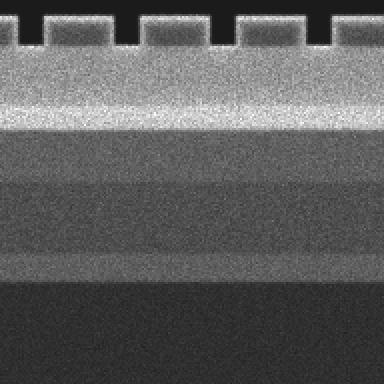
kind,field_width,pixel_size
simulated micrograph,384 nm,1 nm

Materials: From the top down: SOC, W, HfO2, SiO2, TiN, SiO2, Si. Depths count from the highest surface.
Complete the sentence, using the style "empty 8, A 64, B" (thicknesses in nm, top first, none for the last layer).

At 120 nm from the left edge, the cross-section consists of empty 30, W 60, HfO2 24, SiO2 52, TiN 72, SiO2 28, Si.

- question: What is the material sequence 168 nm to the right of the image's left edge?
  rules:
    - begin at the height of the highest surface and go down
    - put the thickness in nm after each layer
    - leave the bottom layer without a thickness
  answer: SOC 30, W 60, HfO2 24, SiO2 52, TiN 72, SiO2 28, Si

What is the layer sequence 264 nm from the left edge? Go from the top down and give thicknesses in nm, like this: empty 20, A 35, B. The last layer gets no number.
SOC 30, W 60, HfO2 24, SiO2 52, TiN 72, SiO2 28, Si